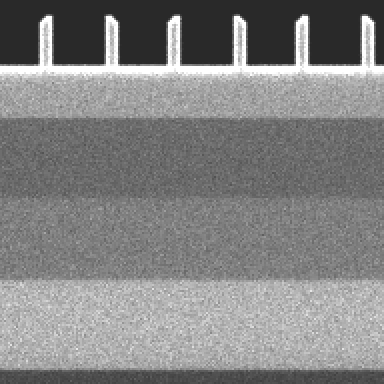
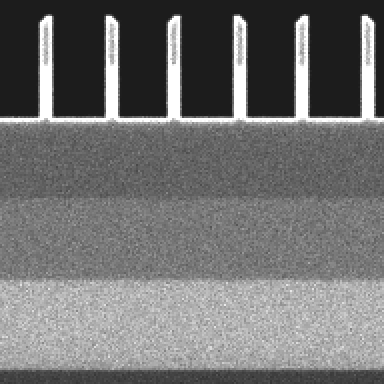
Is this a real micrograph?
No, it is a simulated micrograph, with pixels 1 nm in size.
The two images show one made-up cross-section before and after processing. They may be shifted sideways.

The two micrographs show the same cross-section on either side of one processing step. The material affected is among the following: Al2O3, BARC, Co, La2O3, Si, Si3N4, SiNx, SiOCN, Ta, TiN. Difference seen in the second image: Al2O3 removed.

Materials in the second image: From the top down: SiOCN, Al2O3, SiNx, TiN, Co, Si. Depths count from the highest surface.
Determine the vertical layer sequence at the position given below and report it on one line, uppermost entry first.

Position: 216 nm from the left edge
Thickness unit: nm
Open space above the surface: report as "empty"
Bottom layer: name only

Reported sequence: empty 102, SiNx 80, TiN 82, Co 90, Si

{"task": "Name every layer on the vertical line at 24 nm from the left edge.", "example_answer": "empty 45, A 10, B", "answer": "empty 102, SiNx 80, TiN 82, Co 90, Si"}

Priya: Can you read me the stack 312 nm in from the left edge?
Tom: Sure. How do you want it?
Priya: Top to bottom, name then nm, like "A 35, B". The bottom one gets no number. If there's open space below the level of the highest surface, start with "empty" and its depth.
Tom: empty 102, SiNx 80, TiN 82, Co 90, Si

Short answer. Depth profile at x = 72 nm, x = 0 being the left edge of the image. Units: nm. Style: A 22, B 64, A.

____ empty 102, SiNx 80, TiN 82, Co 90, Si